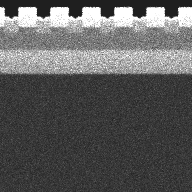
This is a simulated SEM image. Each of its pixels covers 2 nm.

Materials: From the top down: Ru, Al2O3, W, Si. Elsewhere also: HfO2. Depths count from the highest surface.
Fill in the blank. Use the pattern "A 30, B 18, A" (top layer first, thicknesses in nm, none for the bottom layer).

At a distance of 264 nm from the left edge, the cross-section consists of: empty 18, Ru 32, Al2O3 34, W 48, Si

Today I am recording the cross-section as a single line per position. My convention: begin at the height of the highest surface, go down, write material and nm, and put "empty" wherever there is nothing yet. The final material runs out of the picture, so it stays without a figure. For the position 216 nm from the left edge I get empty 22, Ru 28, Al2O3 34, W 48, Si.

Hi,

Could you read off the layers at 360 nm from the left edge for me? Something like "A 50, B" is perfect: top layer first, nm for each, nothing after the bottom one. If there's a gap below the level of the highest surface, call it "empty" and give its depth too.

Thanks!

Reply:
HfO2 38, Al2O3 46, W 48, Si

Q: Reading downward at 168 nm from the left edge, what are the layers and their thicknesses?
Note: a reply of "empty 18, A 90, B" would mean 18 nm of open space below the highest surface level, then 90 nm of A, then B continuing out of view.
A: HfO2 38, Al2O3 46, W 48, Si